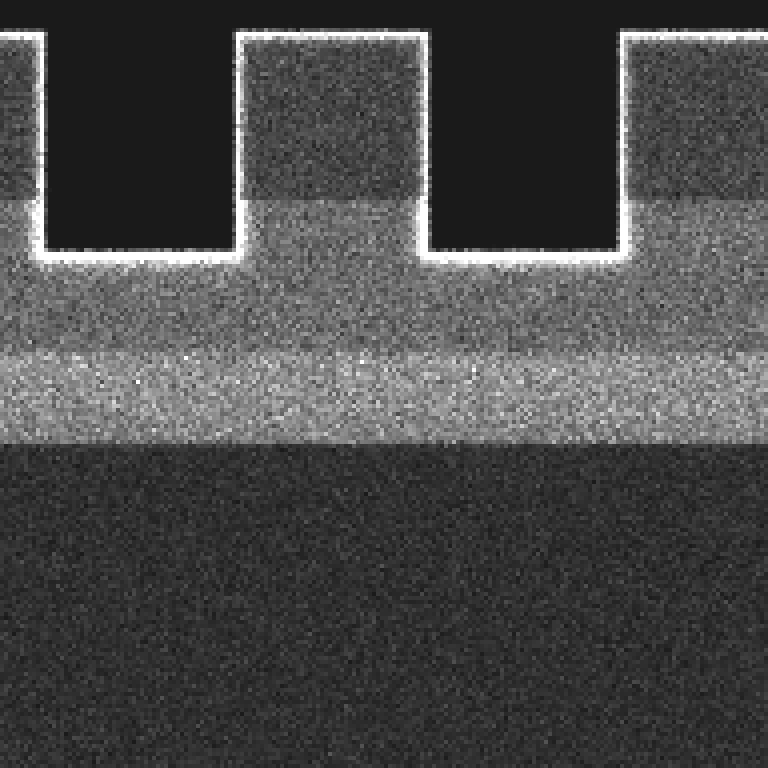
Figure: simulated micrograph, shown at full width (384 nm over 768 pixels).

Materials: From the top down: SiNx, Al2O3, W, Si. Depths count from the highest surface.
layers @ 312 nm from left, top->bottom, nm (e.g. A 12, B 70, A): SiNx 84, Al2O3 76, W 46, Si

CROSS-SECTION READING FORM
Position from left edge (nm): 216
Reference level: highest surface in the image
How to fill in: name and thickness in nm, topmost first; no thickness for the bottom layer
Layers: empty 110, Al2O3 50, W 46, Si